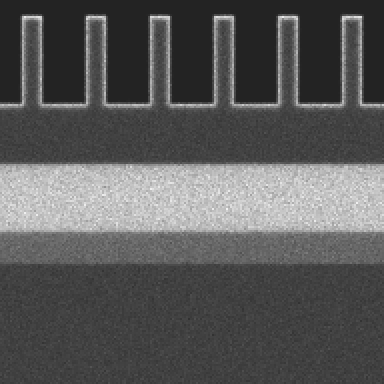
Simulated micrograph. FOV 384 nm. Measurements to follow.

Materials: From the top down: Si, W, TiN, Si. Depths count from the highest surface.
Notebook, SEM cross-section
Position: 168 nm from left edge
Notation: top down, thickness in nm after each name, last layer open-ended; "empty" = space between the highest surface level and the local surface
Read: Si 148, W 68, TiN 32, Si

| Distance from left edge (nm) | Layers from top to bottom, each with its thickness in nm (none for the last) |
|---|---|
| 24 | Si 148, W 68, TiN 32, Si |